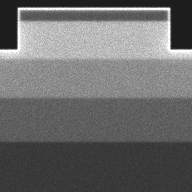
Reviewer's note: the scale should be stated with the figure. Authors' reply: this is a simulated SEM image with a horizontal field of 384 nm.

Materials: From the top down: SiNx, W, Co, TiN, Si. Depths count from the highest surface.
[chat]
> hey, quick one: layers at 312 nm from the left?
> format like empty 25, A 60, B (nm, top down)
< SiNx 26, W 76, Co 78, TiN 88, Si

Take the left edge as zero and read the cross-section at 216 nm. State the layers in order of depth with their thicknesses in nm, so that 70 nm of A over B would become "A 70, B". SiNx 26, W 76, Co 78, TiN 88, Si